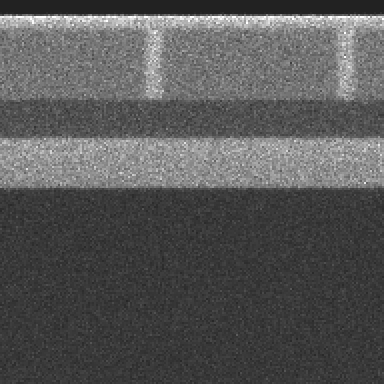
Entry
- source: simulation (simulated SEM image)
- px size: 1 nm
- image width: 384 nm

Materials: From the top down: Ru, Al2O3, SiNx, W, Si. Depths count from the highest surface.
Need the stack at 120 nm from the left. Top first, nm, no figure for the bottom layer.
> Ru 12, Al2O3 72, SiNx 38, W 50, Si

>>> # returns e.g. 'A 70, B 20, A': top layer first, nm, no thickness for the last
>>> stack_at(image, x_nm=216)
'Ru 12, Al2O3 72, SiNx 38, W 50, Si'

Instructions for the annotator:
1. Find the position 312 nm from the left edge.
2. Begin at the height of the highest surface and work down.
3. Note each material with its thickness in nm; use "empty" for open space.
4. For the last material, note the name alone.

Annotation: Ru 12, Al2O3 72, SiNx 38, W 50, Si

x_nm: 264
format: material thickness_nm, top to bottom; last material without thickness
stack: Ru 12, Al2O3 72, SiNx 38, W 50, Si